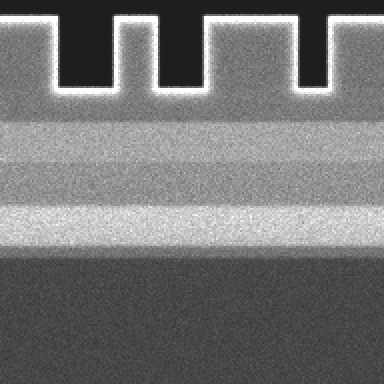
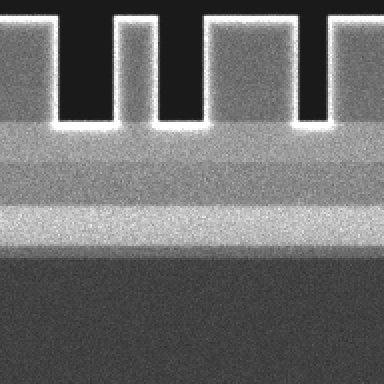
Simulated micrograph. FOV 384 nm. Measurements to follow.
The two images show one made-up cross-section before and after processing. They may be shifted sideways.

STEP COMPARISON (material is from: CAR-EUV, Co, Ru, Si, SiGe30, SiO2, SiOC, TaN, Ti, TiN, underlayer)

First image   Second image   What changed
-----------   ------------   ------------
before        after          underlayer, removed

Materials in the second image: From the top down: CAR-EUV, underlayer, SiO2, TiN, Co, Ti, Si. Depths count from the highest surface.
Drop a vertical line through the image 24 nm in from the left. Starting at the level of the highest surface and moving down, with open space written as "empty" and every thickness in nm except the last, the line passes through CAR-EUV 72, underlayer 34, SiO2 40, TiN 44, Co 40, Ti 12, Si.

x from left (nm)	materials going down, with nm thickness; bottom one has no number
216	CAR-EUV 72, underlayer 34, SiO2 40, TiN 44, Co 40, Ti 12, Si